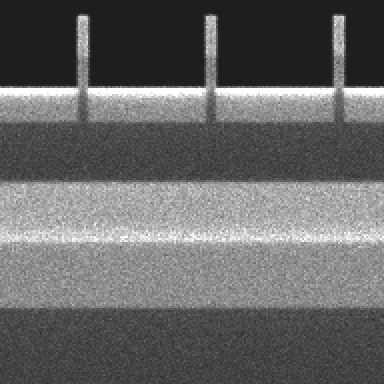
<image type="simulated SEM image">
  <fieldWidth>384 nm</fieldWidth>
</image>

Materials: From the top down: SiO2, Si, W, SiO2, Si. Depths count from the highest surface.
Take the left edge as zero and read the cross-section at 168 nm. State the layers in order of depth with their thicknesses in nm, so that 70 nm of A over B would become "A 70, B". empty 72, SiO2 34, Si 60, W 60, SiO2 66, Si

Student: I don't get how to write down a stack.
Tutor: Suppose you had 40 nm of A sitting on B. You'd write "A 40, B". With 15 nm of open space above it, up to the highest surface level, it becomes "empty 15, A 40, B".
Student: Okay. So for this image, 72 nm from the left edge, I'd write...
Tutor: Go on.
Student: empty 72, SiO2 34, Si 60, W 60, SiO2 66, Si